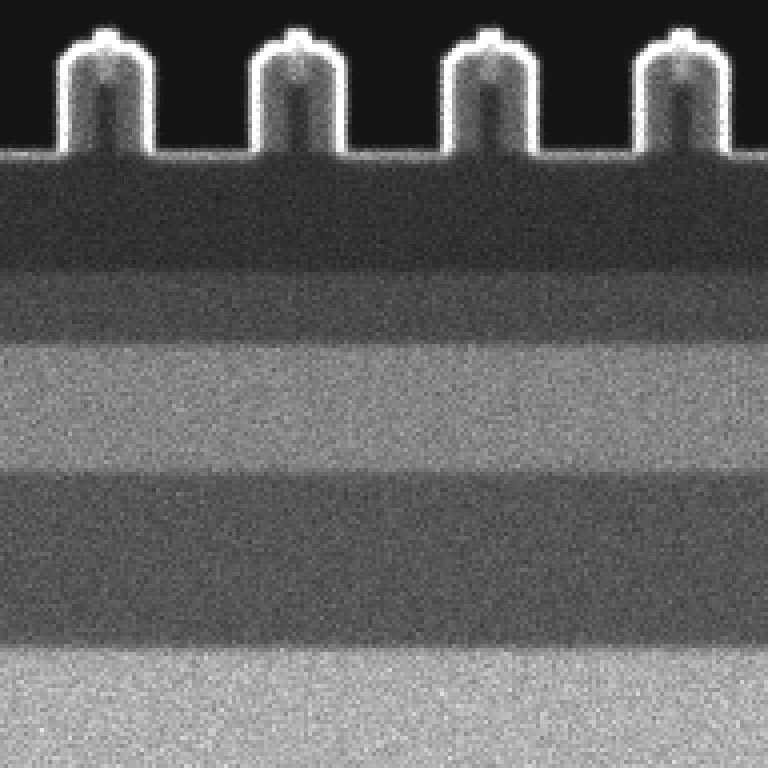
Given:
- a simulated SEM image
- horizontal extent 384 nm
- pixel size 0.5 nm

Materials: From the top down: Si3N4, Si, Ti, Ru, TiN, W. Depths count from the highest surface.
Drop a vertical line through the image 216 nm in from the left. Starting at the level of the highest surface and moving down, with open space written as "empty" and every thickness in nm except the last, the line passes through empty 60, Si 60, Ti 36, Ru 64, TiN 88, W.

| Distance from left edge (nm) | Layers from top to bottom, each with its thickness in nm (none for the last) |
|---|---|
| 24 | empty 60, Si 60, Ti 36, Ru 64, TiN 88, W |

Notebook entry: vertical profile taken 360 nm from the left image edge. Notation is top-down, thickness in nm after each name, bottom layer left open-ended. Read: empty 12, Si3N4 48, Si 60, Ti 36, Ru 64, TiN 88, W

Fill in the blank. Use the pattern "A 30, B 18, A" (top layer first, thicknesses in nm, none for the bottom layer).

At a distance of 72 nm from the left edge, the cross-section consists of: empty 12, Si3N4 48, Si 60, Ti 36, Ru 64, TiN 88, W